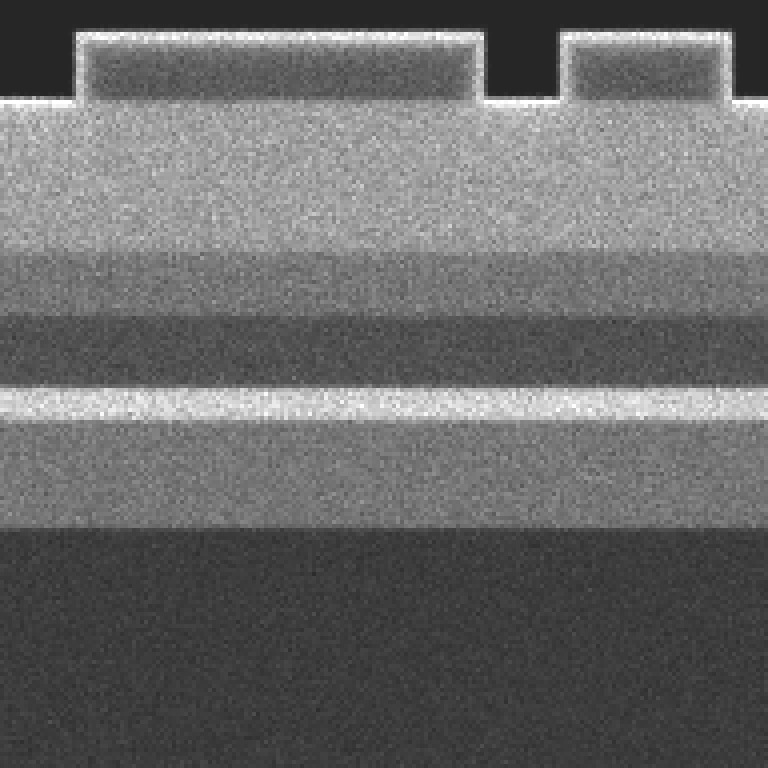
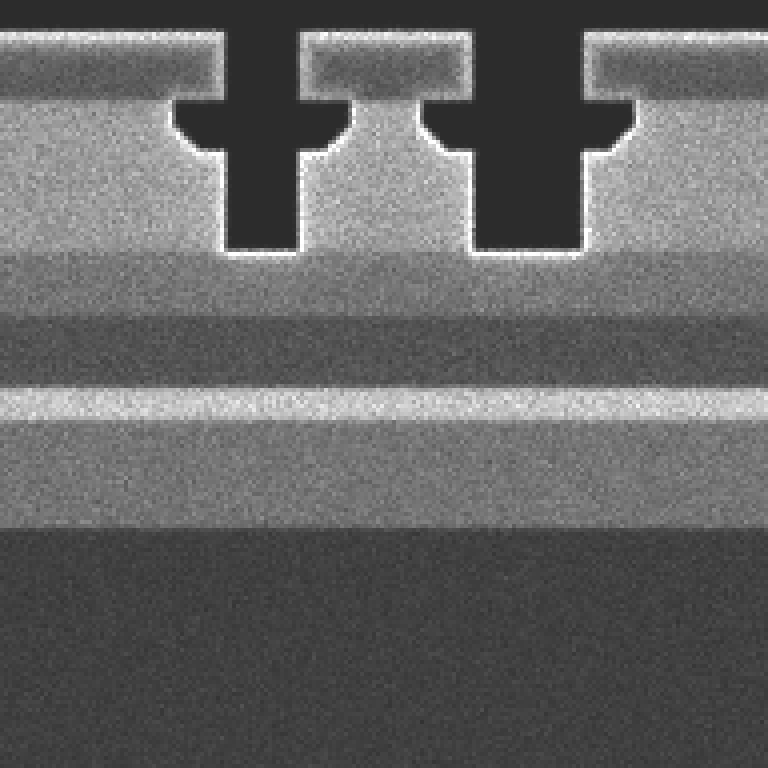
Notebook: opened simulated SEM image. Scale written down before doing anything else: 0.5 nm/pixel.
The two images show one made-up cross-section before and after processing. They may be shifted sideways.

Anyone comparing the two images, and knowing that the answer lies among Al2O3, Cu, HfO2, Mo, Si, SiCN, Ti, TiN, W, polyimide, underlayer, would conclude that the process removed W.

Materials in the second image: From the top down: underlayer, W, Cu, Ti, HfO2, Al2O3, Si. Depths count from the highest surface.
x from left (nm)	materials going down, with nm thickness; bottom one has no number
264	empty 110, Cu 32, Ti 36, HfO2 16, Al2O3 54, Si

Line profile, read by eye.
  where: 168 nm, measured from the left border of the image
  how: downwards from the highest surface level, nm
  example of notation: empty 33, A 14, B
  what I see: underlayer 34, empty 20, W 56, Cu 32, Ti 36, HfO2 16, Al2O3 54, Si